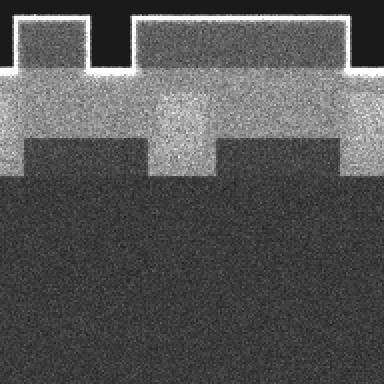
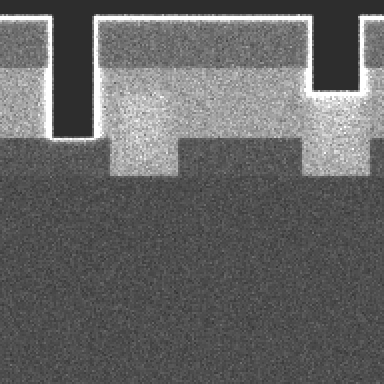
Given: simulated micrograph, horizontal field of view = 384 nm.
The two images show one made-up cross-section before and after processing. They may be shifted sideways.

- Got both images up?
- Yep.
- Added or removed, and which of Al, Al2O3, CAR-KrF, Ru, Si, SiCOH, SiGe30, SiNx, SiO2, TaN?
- removed, SiO2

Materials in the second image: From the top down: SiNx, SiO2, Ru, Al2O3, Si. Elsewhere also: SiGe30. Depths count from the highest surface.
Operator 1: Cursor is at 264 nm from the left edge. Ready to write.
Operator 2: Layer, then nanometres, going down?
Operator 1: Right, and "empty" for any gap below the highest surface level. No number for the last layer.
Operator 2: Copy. SiNx 52, SiO2 70, SiGe30 38, Si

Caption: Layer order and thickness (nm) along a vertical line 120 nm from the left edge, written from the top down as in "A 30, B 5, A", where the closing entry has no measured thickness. SiNx 52, SiO2 24, Ru 72, Al2O3 12, Si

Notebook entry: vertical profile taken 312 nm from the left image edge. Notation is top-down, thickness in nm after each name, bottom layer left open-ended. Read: empty 76, Ru 72, Al2O3 12, Si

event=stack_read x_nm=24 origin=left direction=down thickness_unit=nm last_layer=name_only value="SiNx 52, SiO2 70, SiGe30 38, Si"